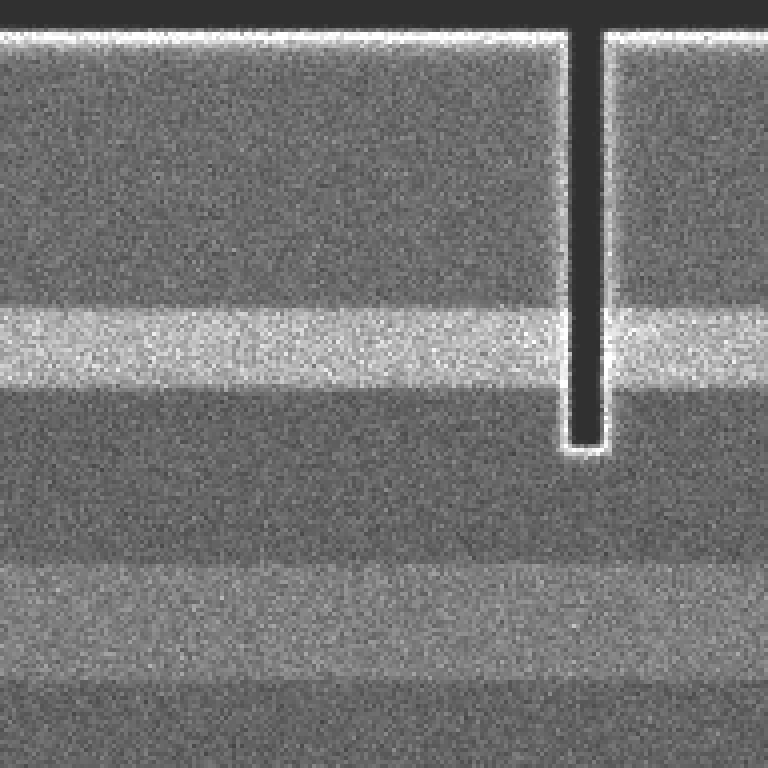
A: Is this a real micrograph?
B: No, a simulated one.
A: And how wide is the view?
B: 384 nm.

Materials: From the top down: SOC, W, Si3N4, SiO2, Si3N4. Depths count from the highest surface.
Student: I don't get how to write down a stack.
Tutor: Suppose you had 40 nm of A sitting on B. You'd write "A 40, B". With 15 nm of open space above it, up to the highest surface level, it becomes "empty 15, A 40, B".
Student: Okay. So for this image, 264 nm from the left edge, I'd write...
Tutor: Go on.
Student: SOC 138, W 40, Si3N4 88, SiO2 58, Si3N4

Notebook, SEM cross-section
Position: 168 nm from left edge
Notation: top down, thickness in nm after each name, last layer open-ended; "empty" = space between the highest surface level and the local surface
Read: SOC 138, W 40, Si3N4 88, SiO2 58, Si3N4